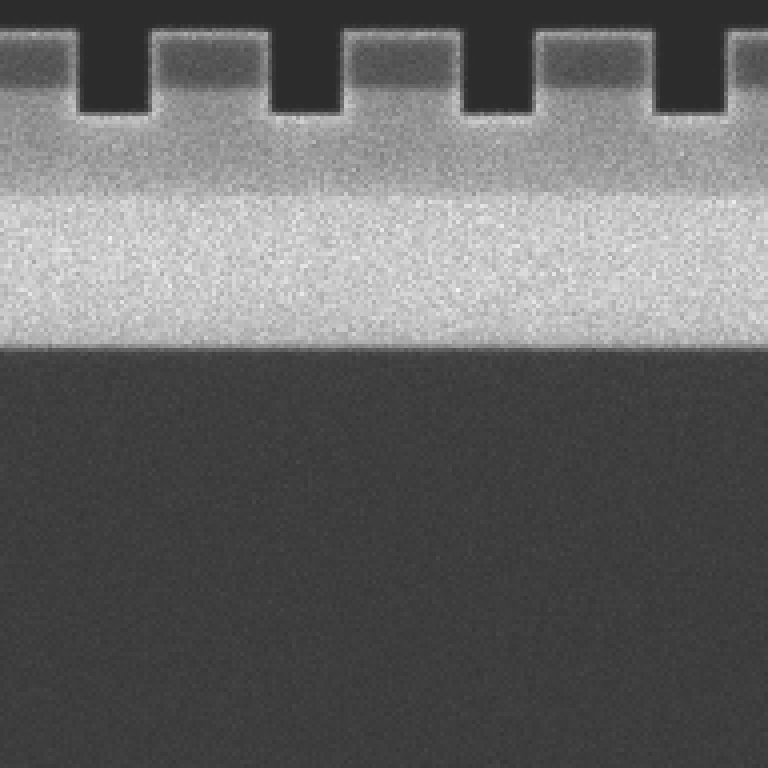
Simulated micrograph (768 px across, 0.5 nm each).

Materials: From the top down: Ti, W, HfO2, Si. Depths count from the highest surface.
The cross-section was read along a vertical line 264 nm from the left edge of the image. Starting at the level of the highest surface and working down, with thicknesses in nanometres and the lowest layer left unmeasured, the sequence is empty 42, W 40, HfO2 76, Si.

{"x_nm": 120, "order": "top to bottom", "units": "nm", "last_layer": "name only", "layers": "Ti 28, W 54, HfO2 76, Si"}